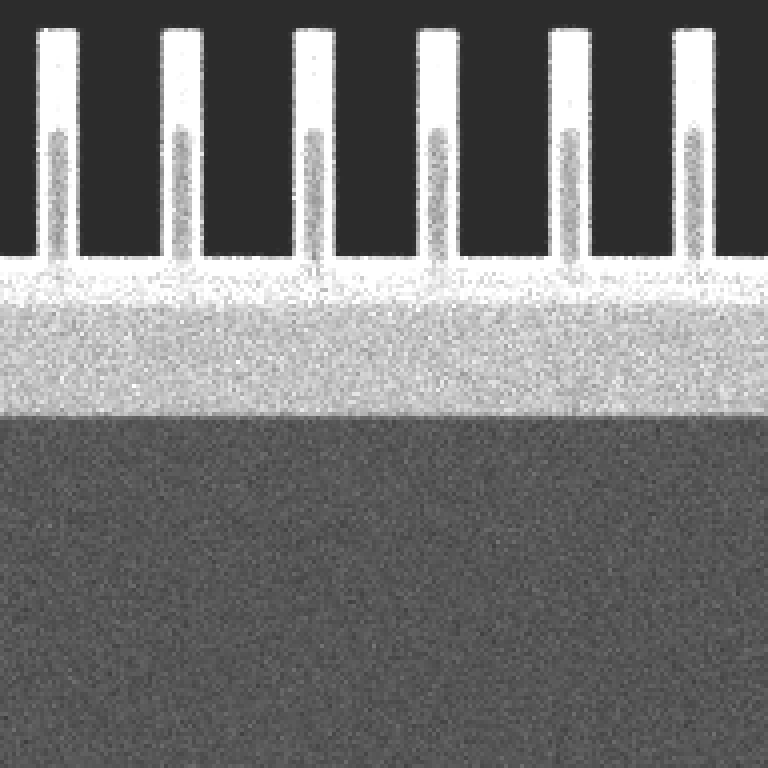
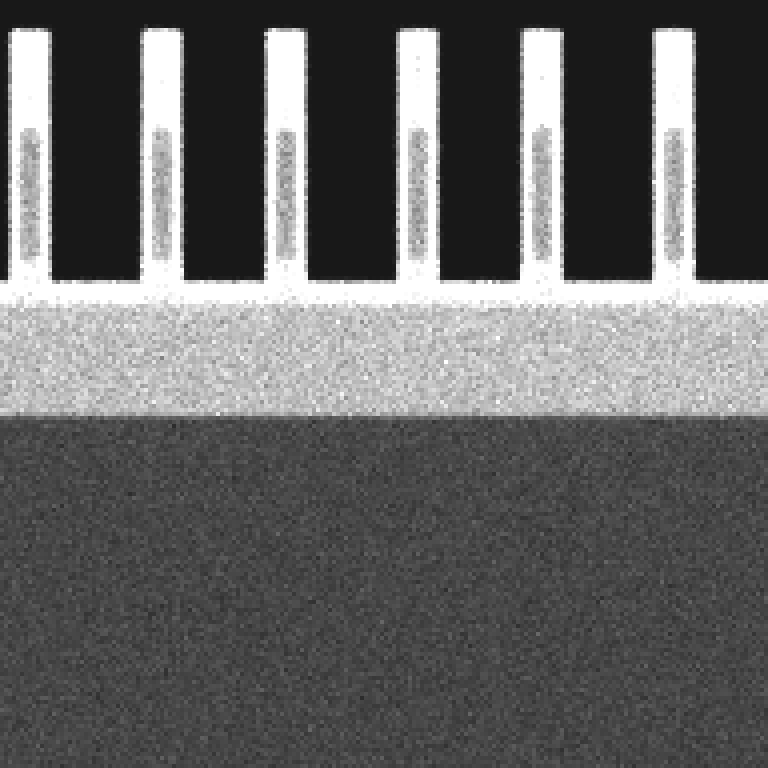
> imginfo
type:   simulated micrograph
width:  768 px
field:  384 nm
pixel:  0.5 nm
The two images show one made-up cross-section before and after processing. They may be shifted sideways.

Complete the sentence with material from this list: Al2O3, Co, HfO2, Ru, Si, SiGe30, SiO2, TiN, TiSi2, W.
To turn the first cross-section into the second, Co must be removed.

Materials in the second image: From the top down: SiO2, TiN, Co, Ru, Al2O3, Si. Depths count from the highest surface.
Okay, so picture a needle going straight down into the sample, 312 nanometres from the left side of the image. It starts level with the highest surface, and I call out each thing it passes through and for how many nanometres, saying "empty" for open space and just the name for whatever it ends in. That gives empty 126, Ru 10, Al2O3 56, Si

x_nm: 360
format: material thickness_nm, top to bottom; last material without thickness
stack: empty 126, Ru 10, Al2O3 56, Si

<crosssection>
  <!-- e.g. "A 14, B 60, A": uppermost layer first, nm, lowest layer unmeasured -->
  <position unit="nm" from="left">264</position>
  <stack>SiO2 48, TiN 66, Co 12, Ru 10, Al2O3 56, Si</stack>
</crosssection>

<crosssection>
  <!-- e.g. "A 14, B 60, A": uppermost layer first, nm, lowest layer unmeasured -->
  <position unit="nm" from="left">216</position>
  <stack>SiO2 48, TiN 66, Co 12, Ru 10, Al2O3 56, Si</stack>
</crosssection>